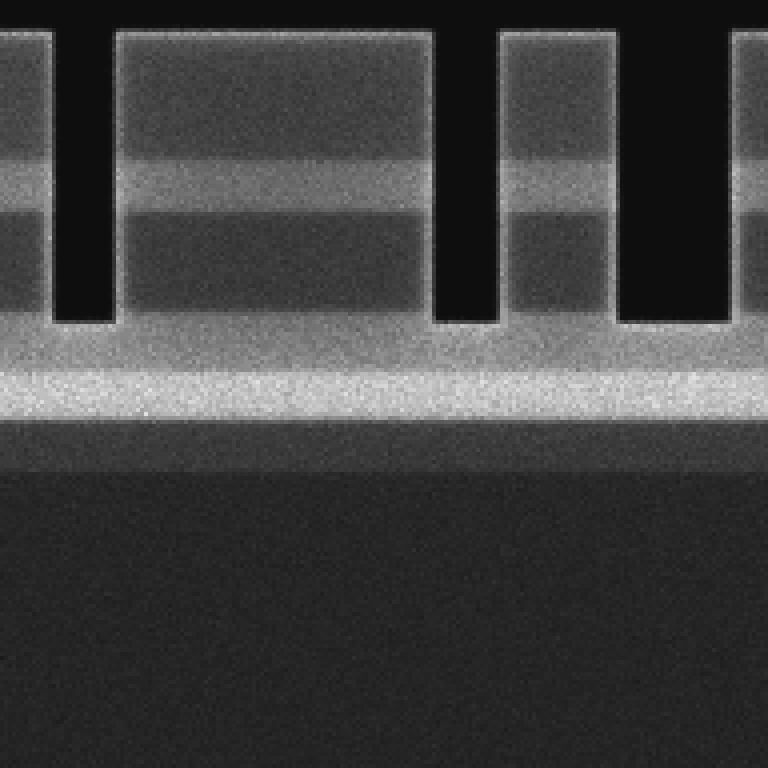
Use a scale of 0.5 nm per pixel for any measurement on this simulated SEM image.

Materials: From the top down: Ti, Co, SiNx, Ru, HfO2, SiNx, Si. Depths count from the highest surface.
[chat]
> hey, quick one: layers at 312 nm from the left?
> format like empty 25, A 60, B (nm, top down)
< empty 146, Ru 24, HfO2 24, SiNx 26, Si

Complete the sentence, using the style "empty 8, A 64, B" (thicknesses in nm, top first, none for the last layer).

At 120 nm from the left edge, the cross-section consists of Ti 64, Co 26, SiNx 50, Ru 30, HfO2 24, SiNx 26, Si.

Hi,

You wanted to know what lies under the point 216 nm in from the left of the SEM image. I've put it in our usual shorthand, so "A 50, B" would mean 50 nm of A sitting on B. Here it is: empty 146, Ru 24, HfO2 24, SiNx 26, Si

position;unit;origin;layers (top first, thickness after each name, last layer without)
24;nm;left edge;Ti 64, Co 26, SiNx 50, Ru 30, HfO2 24, SiNx 26, Si